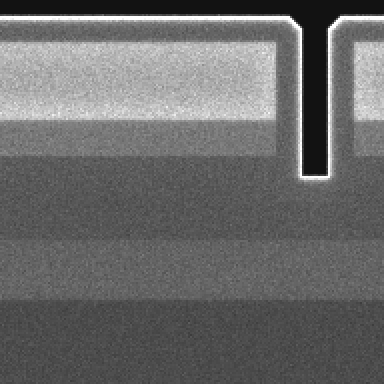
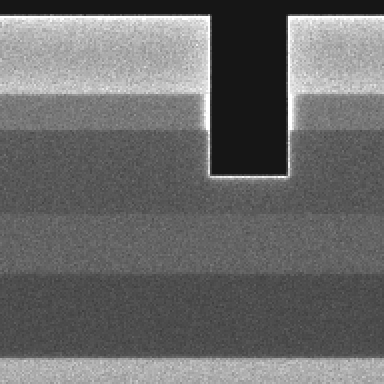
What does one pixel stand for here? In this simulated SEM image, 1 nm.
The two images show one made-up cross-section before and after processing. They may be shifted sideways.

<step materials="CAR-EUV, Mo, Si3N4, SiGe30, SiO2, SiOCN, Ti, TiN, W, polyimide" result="removed Si3N4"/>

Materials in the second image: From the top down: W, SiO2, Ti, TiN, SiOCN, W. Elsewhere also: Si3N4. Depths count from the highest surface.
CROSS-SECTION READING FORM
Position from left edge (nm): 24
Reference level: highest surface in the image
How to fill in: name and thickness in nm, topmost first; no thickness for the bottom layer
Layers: W 78, SiO2 36, Ti 84, TiN 60, SiOCN 84, W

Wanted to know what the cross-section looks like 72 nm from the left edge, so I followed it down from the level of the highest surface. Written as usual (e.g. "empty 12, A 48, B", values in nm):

W 78, SiO2 36, Ti 84, TiN 60, SiOCN 84, W